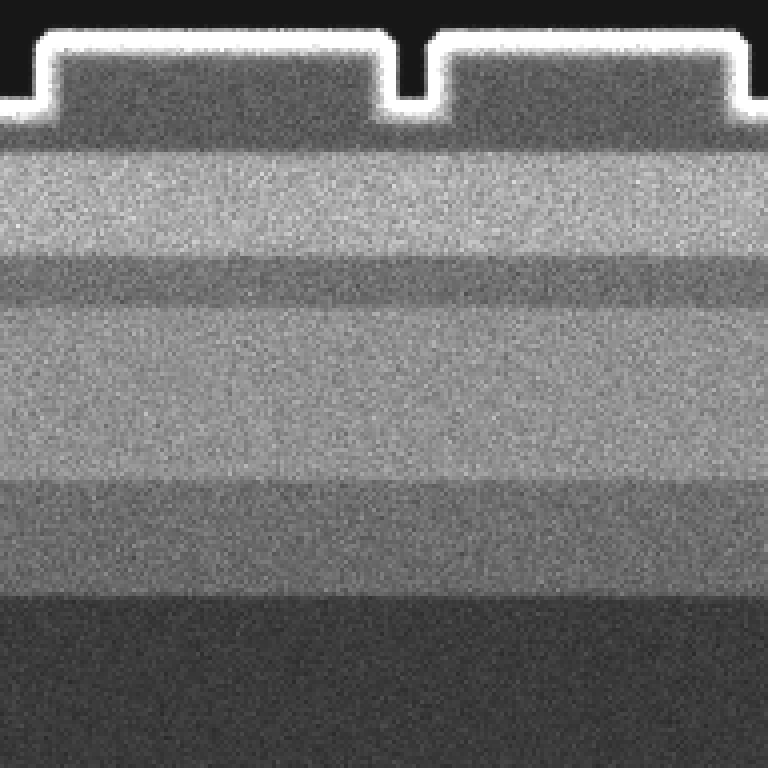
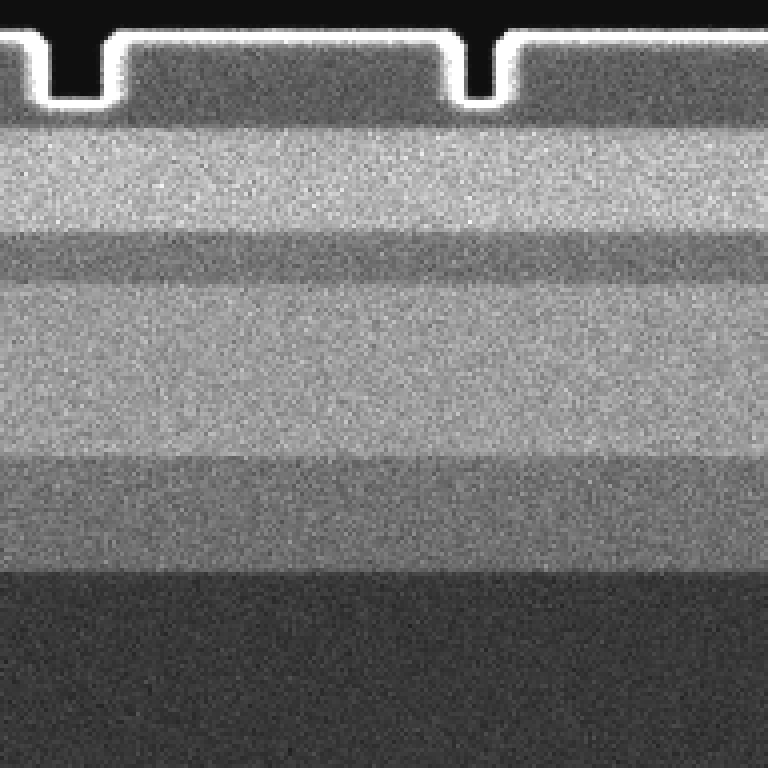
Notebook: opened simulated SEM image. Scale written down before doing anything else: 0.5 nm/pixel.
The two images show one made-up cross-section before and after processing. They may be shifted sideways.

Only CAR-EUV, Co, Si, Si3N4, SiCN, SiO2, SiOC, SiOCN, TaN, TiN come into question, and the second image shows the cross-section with SiO2 removed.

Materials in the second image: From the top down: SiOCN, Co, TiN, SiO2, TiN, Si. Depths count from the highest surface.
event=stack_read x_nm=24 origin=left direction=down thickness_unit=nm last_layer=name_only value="empty 34, SiOCN 14, Co 52, TiN 26, SiO2 86, TiN 58, Si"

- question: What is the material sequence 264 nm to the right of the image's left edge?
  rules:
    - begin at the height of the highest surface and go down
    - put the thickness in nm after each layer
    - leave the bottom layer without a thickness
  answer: SiOCN 48, Co 52, TiN 26, SiO2 86, TiN 58, Si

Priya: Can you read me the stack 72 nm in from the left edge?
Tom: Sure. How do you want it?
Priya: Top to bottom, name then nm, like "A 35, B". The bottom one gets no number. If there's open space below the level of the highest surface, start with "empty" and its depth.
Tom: SiOCN 48, Co 52, TiN 26, SiO2 86, TiN 58, Si